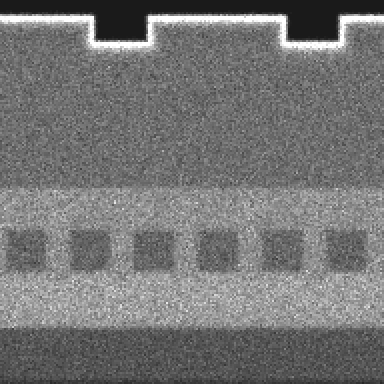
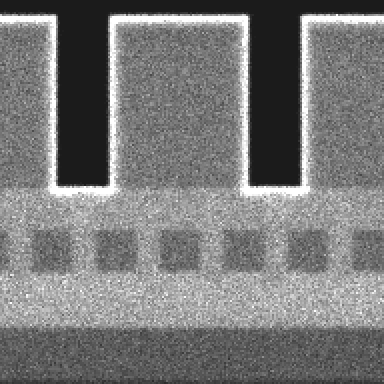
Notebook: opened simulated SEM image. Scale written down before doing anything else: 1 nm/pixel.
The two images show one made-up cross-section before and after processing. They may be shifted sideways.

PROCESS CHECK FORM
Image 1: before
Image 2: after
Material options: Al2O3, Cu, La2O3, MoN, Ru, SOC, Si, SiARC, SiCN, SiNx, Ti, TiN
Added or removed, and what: removed, SOC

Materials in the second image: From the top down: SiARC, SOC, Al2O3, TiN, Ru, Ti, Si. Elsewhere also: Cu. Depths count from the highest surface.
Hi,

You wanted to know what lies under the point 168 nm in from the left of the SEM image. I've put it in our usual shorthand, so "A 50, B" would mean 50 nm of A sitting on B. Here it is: SiARC 26, SOC 146, Al2O3 42, TiN 42, Ru 56, Ti 52, Si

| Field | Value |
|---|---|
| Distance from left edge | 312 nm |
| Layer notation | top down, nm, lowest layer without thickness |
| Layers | SiARC 26, SOC 146, Al2O3 42, TiN 42, Ru 56, Ti 52, Si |